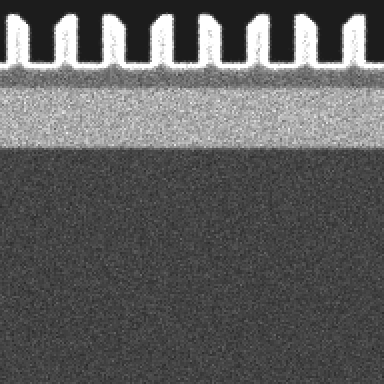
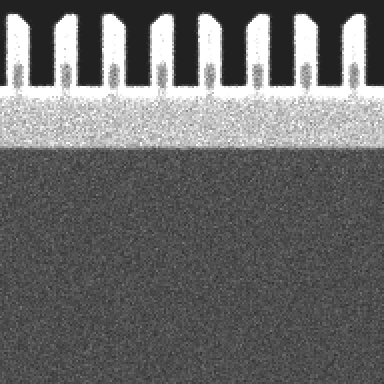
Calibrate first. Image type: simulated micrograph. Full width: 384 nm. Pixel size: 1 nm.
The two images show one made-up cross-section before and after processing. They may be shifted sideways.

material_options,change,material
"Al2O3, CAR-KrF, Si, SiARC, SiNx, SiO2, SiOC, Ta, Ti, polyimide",removed,SiNx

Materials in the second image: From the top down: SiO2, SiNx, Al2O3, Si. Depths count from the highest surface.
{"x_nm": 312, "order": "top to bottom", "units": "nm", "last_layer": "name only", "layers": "empty 8, SiO2 40, SiNx 24, Al2O3 60, Si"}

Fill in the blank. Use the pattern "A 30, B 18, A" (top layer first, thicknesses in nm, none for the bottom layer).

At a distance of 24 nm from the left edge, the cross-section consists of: empty 8, SiO2 40, SiNx 24, Al2O3 60, Si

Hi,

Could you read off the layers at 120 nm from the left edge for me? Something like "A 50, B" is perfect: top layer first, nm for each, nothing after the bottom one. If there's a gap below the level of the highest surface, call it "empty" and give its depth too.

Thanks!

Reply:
empty 8, SiO2 40, SiNx 24, Al2O3 60, Si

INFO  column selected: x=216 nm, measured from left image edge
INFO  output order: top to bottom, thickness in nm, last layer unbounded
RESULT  empty 8, SiO2 40, SiNx 24, Al2O3 60, Si